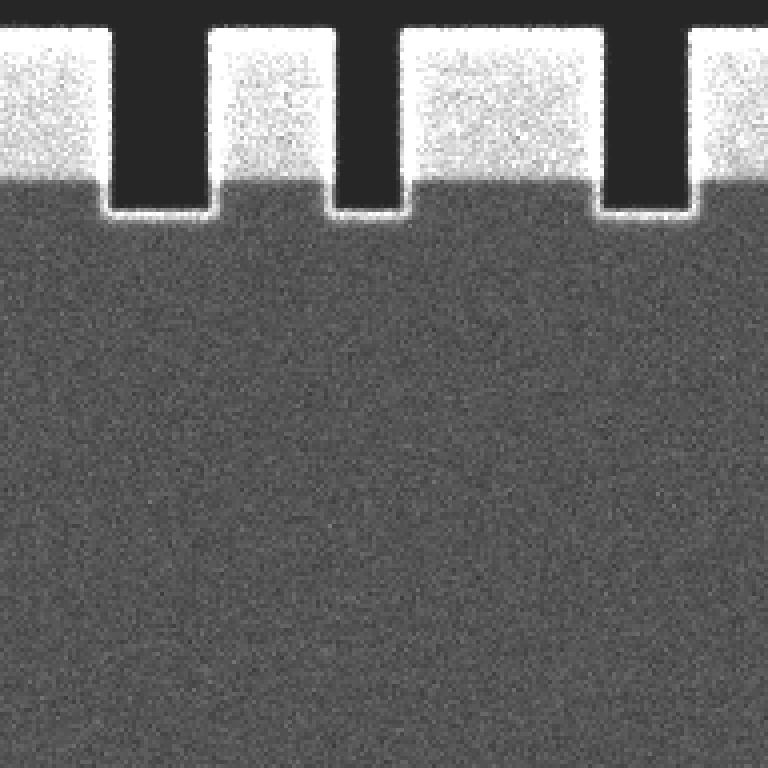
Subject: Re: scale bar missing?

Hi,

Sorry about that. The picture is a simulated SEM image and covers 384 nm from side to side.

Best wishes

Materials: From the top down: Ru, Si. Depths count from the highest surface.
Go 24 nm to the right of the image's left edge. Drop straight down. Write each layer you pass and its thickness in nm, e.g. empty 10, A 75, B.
Ru 74, Si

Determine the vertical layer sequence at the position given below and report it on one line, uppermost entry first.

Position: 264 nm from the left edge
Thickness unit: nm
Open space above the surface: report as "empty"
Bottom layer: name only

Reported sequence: Ru 74, Si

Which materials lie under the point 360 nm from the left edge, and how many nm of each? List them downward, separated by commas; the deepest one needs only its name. Ru 74, Si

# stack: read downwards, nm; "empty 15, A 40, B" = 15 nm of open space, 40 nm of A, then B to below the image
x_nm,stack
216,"Ru 74, Si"